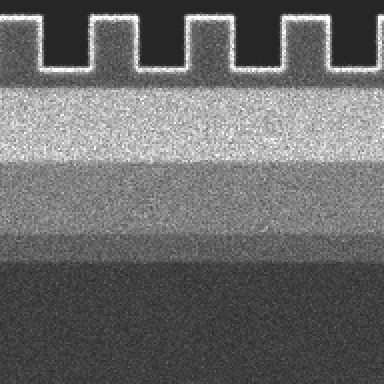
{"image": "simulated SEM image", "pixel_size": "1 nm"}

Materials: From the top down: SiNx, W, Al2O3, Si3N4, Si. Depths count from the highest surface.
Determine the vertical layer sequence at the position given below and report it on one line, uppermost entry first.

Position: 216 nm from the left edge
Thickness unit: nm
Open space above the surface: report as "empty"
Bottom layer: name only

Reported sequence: SiNx 72, W 74, Al2O3 72, Si3N4 28, Si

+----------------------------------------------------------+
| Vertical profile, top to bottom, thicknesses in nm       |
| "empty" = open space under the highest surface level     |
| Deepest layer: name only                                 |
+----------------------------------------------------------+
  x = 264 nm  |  empty 52, SiNx 20, W 74, Al2O3 72, Si3N4 28, Si